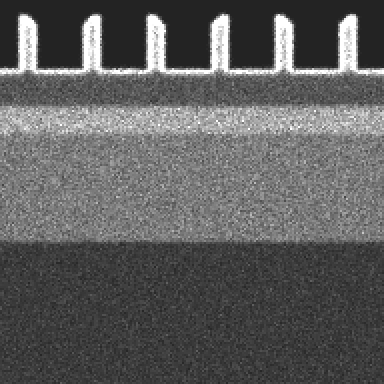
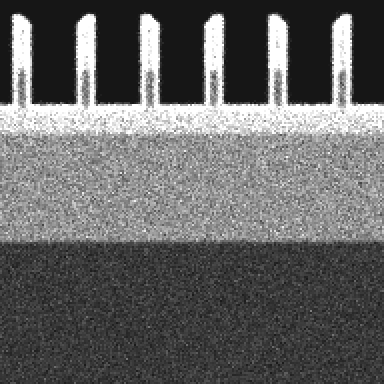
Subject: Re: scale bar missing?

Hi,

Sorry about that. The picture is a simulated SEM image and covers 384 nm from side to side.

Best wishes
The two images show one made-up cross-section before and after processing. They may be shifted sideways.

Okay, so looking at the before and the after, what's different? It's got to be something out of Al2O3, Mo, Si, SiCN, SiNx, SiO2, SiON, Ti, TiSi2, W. SiNx, removed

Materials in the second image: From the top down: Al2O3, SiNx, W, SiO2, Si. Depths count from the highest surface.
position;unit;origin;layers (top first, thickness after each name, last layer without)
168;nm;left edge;empty 90, W 28, SiO2 108, Si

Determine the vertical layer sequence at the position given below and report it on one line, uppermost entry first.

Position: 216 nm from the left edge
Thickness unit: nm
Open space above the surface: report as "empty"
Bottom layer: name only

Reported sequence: Al2O3 54, SiNx 36, W 28, SiO2 108, Si